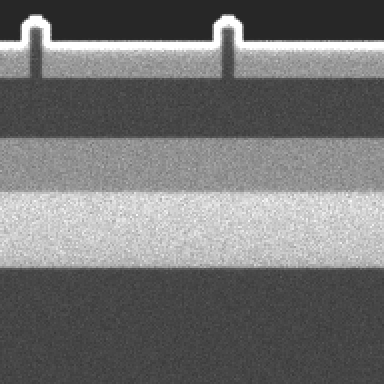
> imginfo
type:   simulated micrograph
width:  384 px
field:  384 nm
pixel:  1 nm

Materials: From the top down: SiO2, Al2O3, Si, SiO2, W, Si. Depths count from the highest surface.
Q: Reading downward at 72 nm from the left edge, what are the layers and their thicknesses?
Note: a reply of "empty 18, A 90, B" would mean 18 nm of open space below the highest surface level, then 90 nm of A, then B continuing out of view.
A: empty 26, SiO2 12, Al2O3 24, Si 60, SiO2 54, W 76, Si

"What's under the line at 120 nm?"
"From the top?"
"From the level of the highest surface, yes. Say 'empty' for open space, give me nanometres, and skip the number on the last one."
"empty 26, SiO2 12, Al2O3 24, Si 60, SiO2 54, W 76, Si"